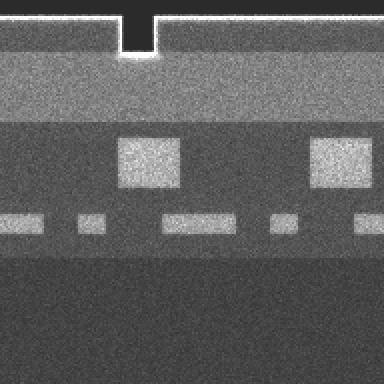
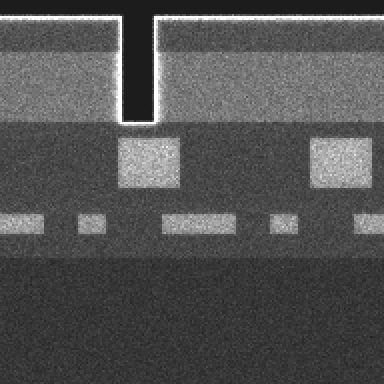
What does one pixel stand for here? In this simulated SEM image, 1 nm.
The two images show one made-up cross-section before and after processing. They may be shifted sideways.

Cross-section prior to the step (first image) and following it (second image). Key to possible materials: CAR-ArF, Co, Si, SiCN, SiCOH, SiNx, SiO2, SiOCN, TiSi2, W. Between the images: SiO2 was removed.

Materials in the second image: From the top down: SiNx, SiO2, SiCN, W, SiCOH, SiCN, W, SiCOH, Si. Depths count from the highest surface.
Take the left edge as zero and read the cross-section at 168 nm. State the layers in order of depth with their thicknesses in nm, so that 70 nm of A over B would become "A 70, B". SiNx 36, SiO2 70, SiCN 16, W 50, SiCOH 16, SiCN 10, W 20, SiCOH 24, Si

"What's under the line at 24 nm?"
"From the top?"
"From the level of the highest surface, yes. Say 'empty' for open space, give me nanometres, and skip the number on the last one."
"SiNx 36, SiO2 70, SiCN 16, SiCOH 66, SiCN 10, W 20, SiCOH 24, Si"